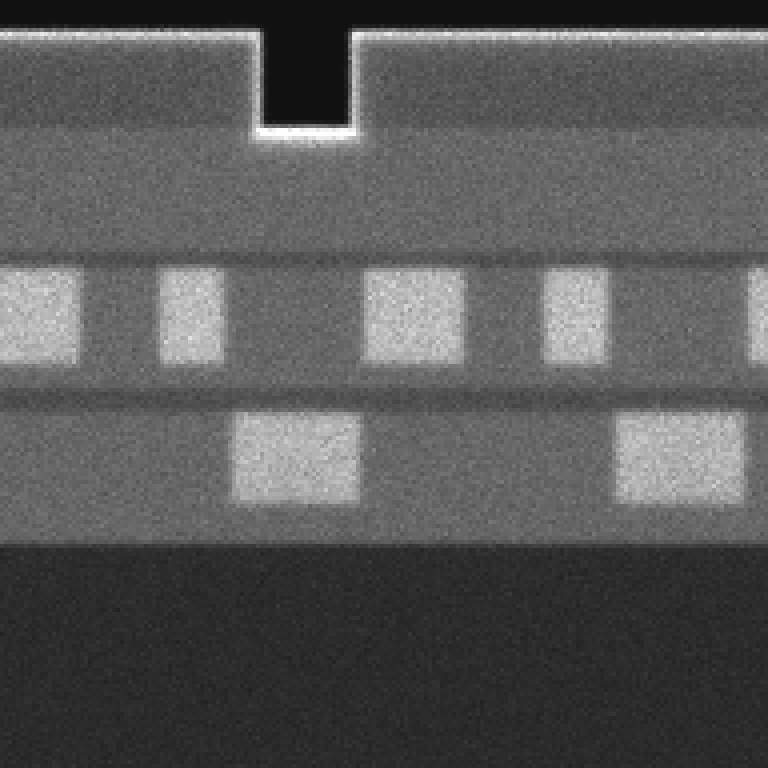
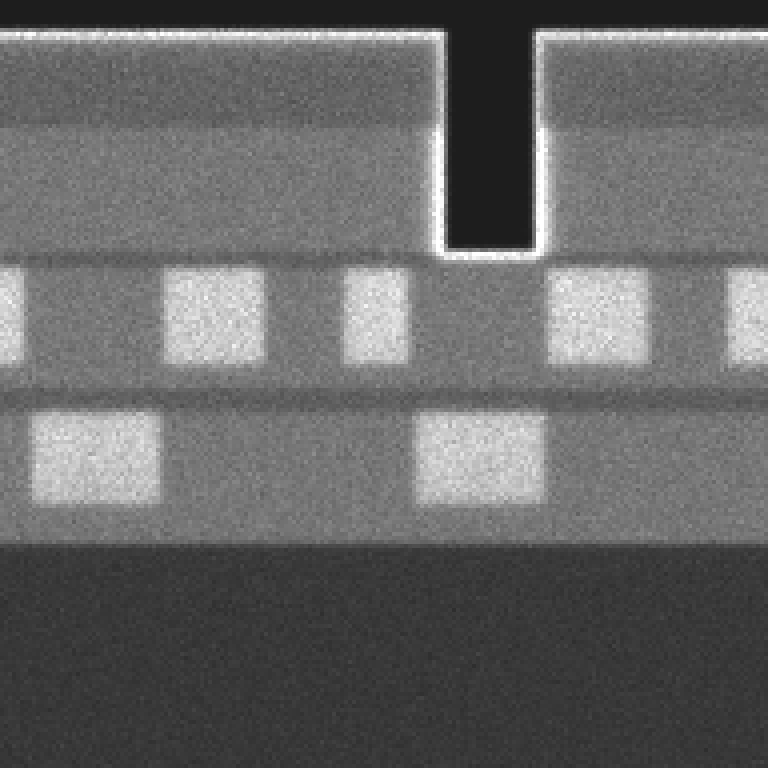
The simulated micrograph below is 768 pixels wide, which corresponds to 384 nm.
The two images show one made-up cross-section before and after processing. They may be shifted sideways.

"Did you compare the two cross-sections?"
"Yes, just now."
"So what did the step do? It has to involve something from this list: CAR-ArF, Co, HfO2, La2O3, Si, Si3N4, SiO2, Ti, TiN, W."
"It removed SiO2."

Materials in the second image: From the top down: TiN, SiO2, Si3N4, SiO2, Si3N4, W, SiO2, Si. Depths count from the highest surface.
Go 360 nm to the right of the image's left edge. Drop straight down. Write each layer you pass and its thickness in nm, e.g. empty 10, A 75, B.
TiN 48, SiO2 62, Si3N4 8, SiO2 60, Si3N4 12, SiO2 66, Si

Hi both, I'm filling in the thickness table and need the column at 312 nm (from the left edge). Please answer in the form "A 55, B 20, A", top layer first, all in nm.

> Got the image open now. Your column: TiN 48, SiO2 62, Si3N4 8, W 48, SiO2 12, Si3N4 12, SiO2 66, Si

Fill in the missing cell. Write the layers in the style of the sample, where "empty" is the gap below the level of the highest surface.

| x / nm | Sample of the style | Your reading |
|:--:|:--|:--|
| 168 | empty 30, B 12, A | TiN 48, SiO2 62, Si3N4 8, SiO2 60, Si3N4 12, SiO2 66, Si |